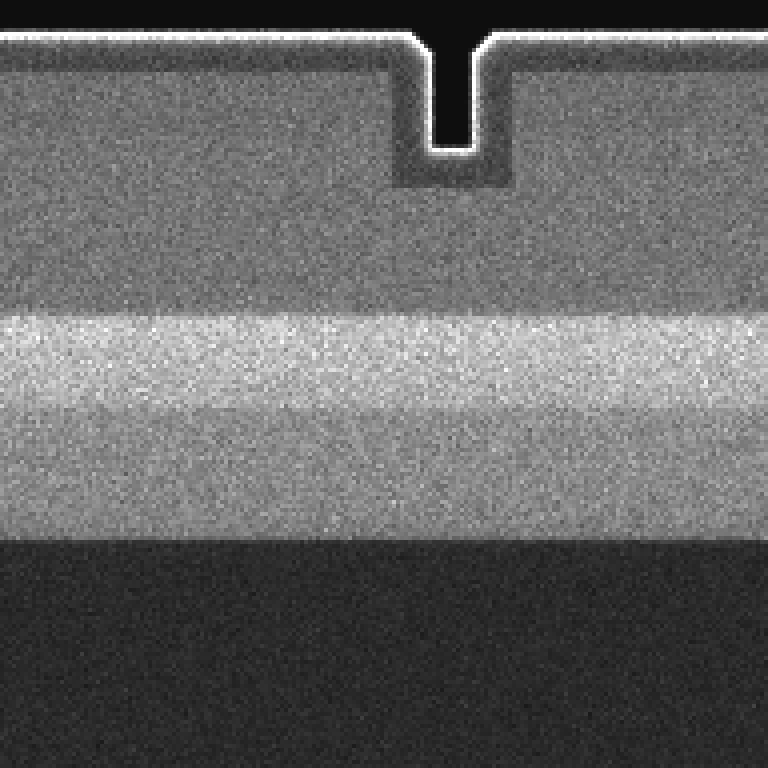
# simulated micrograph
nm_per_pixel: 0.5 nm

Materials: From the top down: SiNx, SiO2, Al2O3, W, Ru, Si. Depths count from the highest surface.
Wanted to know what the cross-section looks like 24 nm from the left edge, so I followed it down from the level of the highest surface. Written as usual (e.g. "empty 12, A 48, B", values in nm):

SiNx 20, SiO2 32, Al2O3 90, W 46, Ru 66, Si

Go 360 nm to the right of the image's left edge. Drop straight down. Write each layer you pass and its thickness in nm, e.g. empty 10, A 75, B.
SiNx 20, SiO2 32, Al2O3 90, W 46, Ru 66, Si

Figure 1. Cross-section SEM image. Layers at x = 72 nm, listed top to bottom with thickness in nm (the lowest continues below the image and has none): SiNx 20, SiO2 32, Al2O3 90, W 46, Ru 66, Si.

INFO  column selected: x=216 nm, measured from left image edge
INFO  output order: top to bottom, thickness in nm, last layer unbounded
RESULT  empty 58, SiNx 20, Al2O3 64, W 46, Ru 66, Si